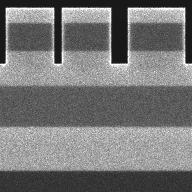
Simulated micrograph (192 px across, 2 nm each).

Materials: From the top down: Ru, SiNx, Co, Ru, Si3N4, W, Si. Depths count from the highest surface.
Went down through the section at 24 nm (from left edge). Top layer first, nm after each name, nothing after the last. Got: Ru 30, SiNx 56, Co 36, Ru 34, Si3N4 82, W 88, Si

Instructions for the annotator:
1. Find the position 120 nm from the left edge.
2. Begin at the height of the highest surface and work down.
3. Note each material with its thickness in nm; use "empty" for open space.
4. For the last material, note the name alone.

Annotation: empty 112, Co 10, Ru 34, Si3N4 82, W 88, Si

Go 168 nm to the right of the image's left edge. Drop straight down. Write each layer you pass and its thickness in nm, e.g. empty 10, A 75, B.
Ru 30, SiNx 56, Co 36, Ru 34, Si3N4 82, W 88, Si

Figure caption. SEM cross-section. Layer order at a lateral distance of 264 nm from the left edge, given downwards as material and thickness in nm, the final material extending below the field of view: Ru 30, SiNx 56, Co 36, Ru 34, Si3N4 82, W 88, Si